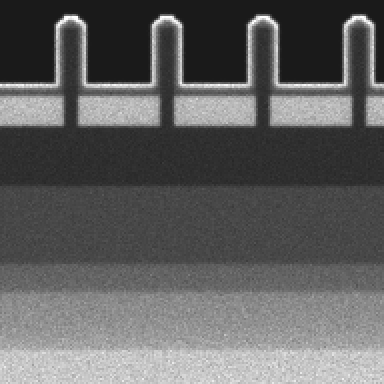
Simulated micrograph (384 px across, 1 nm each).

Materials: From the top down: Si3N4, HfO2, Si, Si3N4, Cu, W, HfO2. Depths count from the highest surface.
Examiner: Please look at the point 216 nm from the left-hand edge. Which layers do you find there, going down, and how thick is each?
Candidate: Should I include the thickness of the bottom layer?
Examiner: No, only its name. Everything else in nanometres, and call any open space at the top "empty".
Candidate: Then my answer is empty 68, Si3N4 12, HfO2 30, Si 60, Si3N4 78, Cu 28, W 58, HfO2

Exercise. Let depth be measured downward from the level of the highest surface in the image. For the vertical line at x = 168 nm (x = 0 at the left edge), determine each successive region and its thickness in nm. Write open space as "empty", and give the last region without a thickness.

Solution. Si3N4 12, Si 158, Si3N4 78, Cu 28, W 58, HfO2